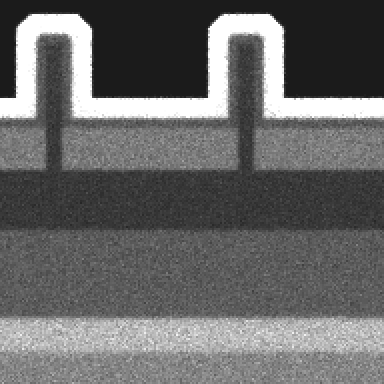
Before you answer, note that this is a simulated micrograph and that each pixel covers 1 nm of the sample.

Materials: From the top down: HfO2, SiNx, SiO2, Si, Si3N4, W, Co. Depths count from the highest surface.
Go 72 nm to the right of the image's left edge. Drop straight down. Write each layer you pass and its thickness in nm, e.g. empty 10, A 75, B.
HfO2 102, SiNx 10, SiO2 42, Si 60, Si3N4 88, W 34, Co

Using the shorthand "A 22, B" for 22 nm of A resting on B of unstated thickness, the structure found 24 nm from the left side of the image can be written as empty 6, HfO2 96, SiNx 10, SiO2 42, Si 60, Si3N4 88, W 34, Co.